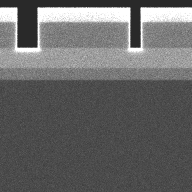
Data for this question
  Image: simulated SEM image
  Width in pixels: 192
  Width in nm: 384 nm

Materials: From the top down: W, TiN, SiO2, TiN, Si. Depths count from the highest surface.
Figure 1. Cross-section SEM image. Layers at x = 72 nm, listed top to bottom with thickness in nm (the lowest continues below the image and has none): empty 80, SiO2 40, TiN 24, Si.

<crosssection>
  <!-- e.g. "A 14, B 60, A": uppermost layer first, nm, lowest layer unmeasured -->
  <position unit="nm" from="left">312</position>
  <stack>W 28, TiN 52, SiO2 40, TiN 24, Si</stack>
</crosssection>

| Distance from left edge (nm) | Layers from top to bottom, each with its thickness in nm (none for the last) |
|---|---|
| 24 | W 28, TiN 52, SiO2 40, TiN 24, Si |